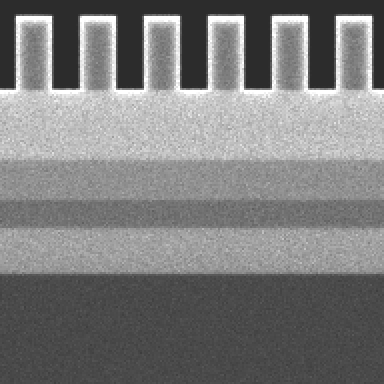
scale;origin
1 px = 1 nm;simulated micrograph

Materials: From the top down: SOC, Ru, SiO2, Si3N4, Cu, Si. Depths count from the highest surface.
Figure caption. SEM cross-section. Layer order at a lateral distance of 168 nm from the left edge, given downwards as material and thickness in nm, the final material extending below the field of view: SOC 74, Ru 70, SiO2 40, Si3N4 28, Cu 46, Si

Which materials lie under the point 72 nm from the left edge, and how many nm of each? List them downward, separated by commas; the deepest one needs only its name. empty 74, Ru 70, SiO2 40, Si3N4 28, Cu 46, Si